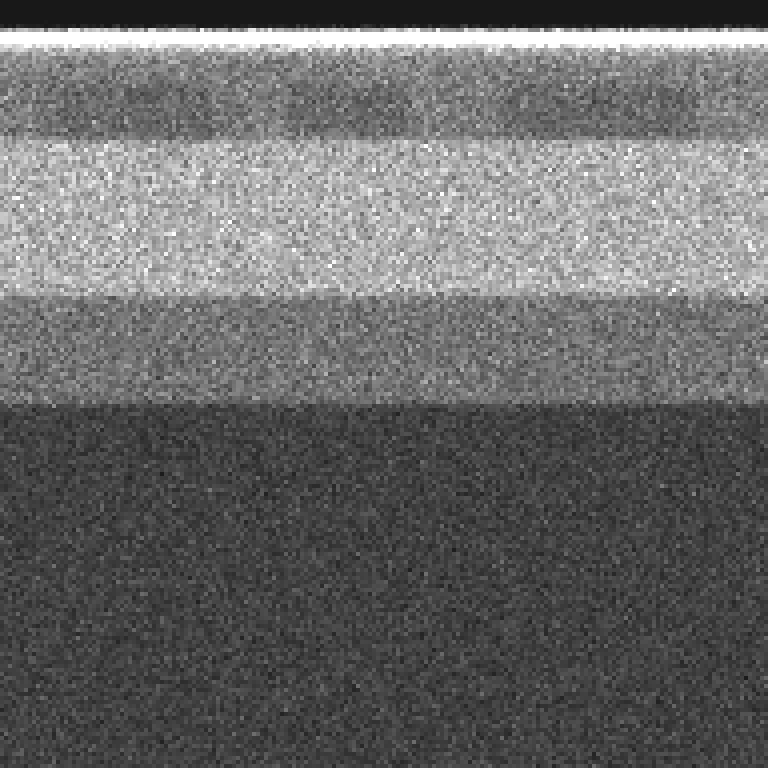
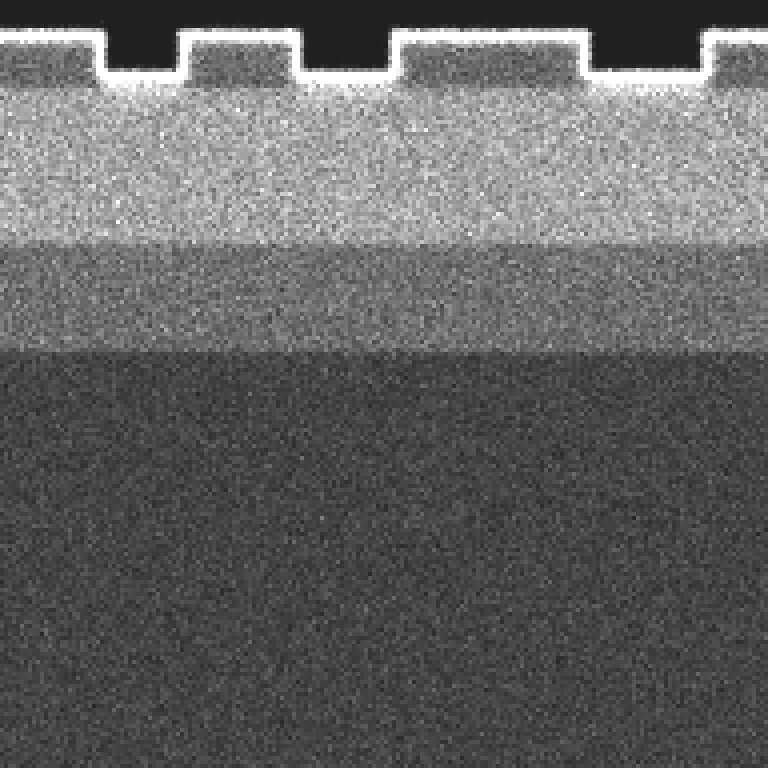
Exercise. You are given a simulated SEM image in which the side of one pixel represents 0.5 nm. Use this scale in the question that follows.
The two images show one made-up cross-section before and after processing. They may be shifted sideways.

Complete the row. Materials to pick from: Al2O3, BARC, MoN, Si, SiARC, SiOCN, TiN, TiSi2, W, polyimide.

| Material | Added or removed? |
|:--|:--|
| SiARC | removed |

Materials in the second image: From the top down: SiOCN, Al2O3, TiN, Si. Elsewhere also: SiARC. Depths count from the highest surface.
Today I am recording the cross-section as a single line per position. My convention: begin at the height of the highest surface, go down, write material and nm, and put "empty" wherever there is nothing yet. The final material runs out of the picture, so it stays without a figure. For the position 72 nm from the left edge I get empty 20, SiARC 8, Al2O3 78, TiN 54, Si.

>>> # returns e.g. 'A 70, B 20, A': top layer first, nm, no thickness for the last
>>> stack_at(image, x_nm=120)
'SiOCN 28, Al2O3 78, TiN 54, Si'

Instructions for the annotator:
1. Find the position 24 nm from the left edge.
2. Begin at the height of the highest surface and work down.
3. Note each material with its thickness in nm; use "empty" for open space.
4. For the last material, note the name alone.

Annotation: SiOCN 28, Al2O3 78, TiN 54, Si